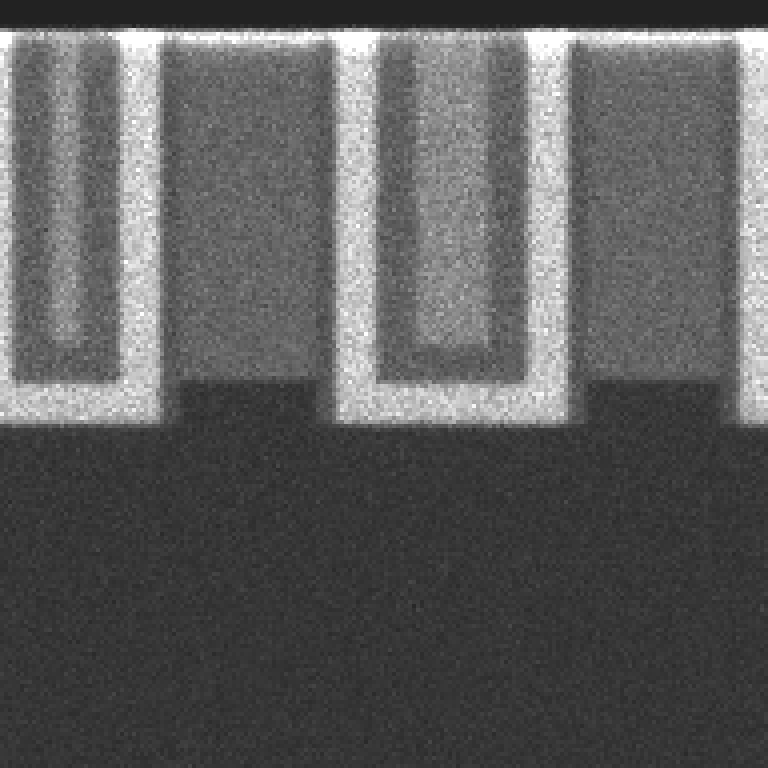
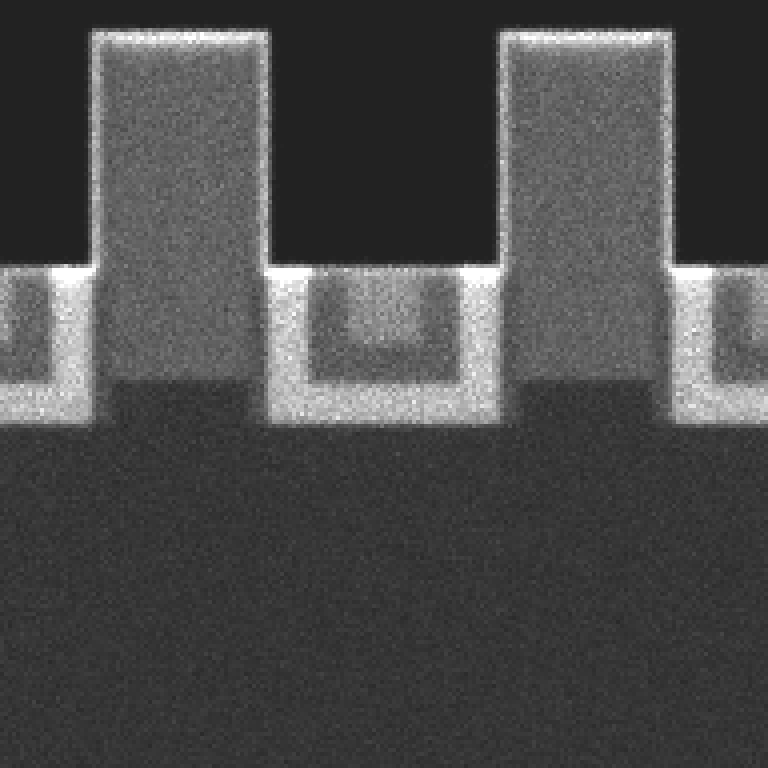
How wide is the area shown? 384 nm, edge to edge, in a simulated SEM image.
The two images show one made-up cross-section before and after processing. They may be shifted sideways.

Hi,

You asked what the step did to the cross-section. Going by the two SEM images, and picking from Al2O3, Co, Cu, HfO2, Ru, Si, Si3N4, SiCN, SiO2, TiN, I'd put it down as HfO2 and Ru and TiN, removed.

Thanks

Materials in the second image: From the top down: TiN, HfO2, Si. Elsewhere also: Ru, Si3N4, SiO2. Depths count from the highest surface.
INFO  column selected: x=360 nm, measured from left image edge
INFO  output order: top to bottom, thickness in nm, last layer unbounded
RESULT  empty 118, TiN 58, HfO2 20, Si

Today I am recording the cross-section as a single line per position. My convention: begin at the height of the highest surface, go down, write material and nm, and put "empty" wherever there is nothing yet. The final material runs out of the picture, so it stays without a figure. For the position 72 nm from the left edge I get SiO2 174, Si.